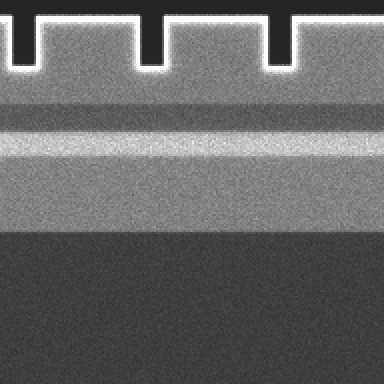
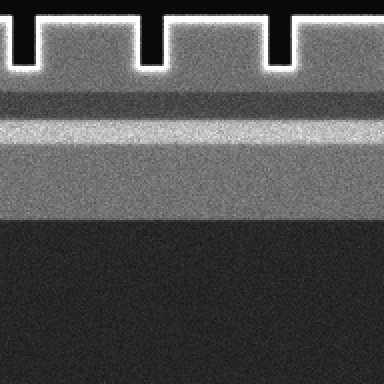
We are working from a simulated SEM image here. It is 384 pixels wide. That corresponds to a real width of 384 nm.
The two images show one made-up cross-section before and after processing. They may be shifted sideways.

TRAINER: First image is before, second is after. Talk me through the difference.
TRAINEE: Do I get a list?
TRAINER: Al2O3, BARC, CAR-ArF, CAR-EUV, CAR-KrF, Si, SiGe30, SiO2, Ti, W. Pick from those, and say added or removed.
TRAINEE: removed: SiO2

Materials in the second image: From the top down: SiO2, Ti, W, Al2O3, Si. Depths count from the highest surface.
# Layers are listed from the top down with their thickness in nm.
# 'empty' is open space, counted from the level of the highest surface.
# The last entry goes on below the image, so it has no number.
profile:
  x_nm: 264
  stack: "SiO2 76, Ti 28, W 24, Al2O3 76, Si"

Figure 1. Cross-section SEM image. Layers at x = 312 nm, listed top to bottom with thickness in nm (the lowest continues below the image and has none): SiO2 76, Ti 28, W 24, Al2O3 76, Si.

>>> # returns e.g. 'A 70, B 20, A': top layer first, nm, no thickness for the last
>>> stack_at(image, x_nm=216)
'SiO2 76, Ti 28, W 24, Al2O3 76, Si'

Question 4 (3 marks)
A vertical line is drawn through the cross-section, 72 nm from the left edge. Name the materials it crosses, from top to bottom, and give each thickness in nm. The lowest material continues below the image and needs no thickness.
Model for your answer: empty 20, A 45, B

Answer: SiO2 76, Ti 28, W 24, Al2O3 76, Si